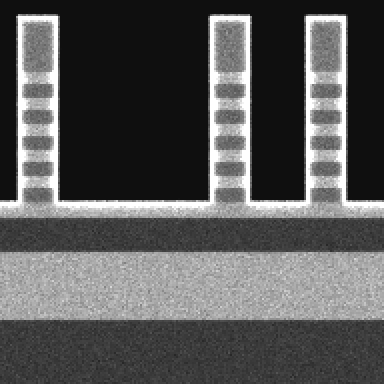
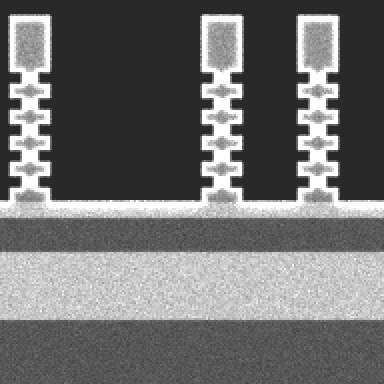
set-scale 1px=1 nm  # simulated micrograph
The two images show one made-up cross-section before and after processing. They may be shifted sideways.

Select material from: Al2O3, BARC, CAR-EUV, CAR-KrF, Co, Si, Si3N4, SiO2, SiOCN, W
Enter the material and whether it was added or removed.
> Al2O3 / removed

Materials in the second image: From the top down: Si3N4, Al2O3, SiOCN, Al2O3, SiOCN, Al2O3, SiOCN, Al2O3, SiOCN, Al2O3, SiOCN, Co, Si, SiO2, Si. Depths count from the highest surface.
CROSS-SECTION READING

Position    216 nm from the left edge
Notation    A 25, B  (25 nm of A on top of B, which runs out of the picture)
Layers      Si3N4 56, Al2O3 12, SiOCN 14, Al2O3 12, SiOCN 14, Al2O3 12, SiOCN 14, Al2O3 12, SiOCN 14, Al2O3 12, SiOCN 14, Co 16, Si 34, SiO2 68, Si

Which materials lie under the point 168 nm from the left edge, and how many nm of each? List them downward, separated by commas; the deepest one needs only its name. empty 186, Co 16, Si 34, SiO2 68, Si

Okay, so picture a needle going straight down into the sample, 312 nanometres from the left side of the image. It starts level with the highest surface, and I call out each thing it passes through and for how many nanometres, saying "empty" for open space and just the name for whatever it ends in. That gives Si3N4 56, Al2O3 12, SiOCN 14, Al2O3 12, SiOCN 14, Al2O3 12, SiOCN 14, Al2O3 12, SiOCN 14, Al2O3 12, SiOCN 14, Co 16, Si 34, SiO2 68, Si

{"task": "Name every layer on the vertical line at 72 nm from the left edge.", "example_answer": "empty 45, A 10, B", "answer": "empty 186, Co 16, Si 34, SiO2 68, Si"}